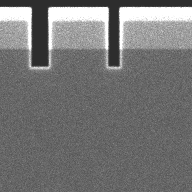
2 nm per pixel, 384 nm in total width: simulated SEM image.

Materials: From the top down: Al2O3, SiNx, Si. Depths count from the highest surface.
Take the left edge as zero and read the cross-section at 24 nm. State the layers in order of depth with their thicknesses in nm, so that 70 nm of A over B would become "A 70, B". Al2O3 26, SiNx 56, Si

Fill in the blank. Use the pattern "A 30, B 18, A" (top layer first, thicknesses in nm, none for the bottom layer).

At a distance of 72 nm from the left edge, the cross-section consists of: empty 118, Si